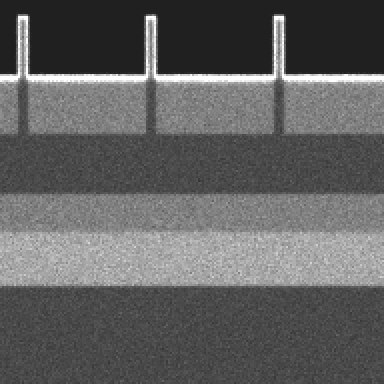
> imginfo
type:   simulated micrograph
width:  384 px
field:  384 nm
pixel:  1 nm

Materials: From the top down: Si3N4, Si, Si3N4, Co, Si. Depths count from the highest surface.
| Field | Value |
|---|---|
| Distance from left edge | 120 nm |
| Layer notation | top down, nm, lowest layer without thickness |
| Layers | empty 60, Si3N4 58, Si 60, Si3N4 38, Co 54, Si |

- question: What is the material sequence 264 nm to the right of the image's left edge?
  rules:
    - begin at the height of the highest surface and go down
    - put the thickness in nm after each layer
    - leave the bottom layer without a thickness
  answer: empty 60, Si3N4 58, Si 60, Si3N4 38, Co 54, Si